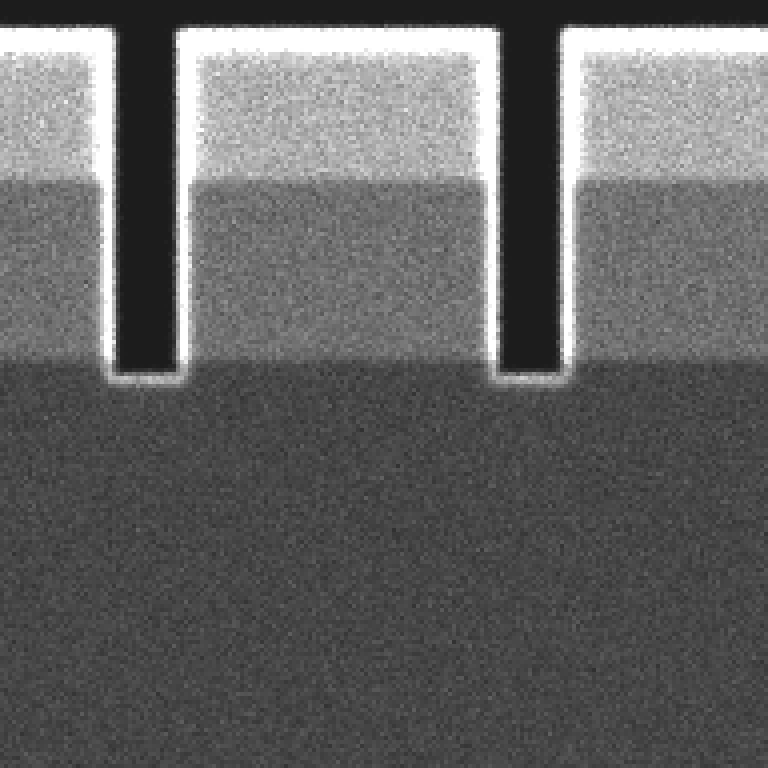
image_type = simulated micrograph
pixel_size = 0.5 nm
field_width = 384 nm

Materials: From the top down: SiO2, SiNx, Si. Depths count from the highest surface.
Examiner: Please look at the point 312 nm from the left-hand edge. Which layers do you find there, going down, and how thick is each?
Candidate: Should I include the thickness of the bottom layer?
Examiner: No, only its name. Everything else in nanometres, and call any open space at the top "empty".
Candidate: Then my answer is SiO2 74, SiNx 90, Si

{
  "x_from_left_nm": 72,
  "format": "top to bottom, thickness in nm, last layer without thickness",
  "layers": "empty 172, Si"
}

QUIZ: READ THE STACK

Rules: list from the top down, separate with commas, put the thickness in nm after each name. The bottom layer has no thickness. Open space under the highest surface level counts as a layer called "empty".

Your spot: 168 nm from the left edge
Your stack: SiO2 74, SiNx 90, Si